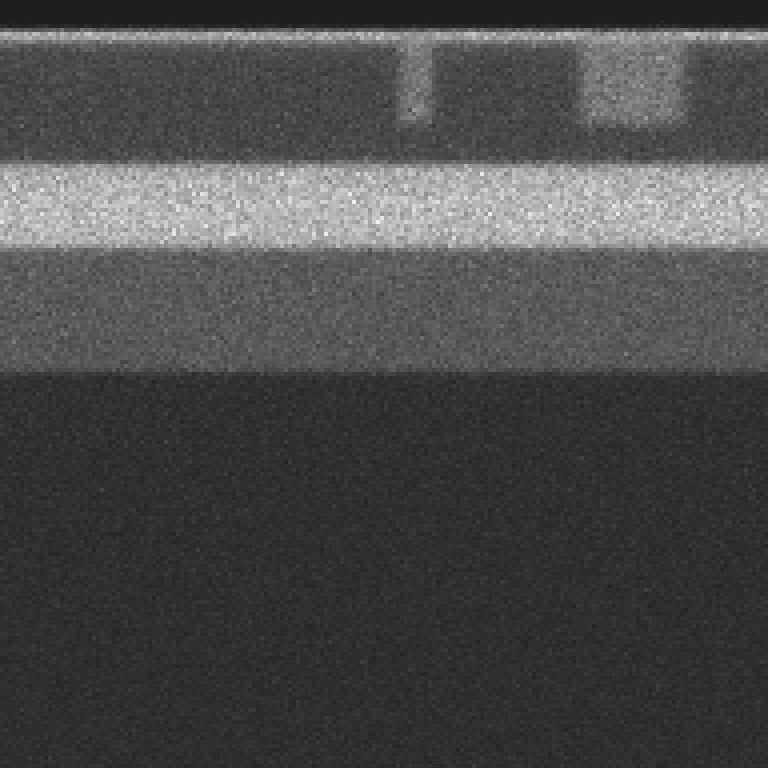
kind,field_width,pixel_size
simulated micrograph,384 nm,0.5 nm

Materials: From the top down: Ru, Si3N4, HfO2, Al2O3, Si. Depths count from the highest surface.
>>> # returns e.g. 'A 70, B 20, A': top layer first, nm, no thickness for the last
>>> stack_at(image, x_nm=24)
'Si3N4 66, HfO2 42, Al2O3 62, Si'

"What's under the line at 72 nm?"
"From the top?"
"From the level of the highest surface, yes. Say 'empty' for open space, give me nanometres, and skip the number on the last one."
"Si3N4 66, HfO2 42, Al2O3 62, Si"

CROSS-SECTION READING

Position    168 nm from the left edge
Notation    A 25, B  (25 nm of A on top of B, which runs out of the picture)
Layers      Si3N4 66, HfO2 42, Al2O3 62, Si